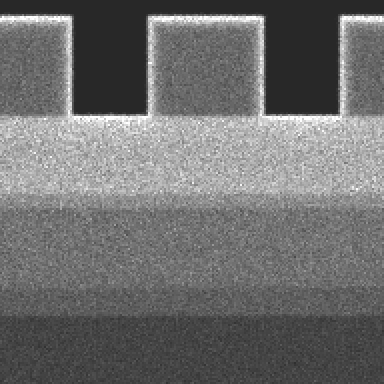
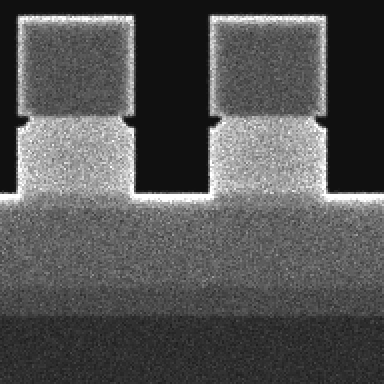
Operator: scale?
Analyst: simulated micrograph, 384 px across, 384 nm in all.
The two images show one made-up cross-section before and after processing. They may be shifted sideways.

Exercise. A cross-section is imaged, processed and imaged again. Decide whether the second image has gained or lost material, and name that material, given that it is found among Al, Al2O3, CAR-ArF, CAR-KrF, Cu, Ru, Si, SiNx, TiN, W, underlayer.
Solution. removed: Ru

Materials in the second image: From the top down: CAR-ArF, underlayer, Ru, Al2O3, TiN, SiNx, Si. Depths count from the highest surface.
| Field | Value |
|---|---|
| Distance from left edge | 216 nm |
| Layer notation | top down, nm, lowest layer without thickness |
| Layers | CAR-ArF 60, underlayer 40, empty 10, Ru 68, Al2O3 14, TiN 80, SiNx 28, Si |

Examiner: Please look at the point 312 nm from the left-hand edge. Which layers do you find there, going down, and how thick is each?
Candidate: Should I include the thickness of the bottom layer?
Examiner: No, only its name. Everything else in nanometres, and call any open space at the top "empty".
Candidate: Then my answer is CAR-ArF 60, underlayer 40, Ru 78, Al2O3 14, TiN 80, SiNx 28, Si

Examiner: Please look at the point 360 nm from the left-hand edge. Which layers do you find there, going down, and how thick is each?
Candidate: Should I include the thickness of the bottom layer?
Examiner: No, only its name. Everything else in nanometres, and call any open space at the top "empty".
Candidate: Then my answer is empty 178, Al2O3 14, TiN 80, SiNx 28, Si